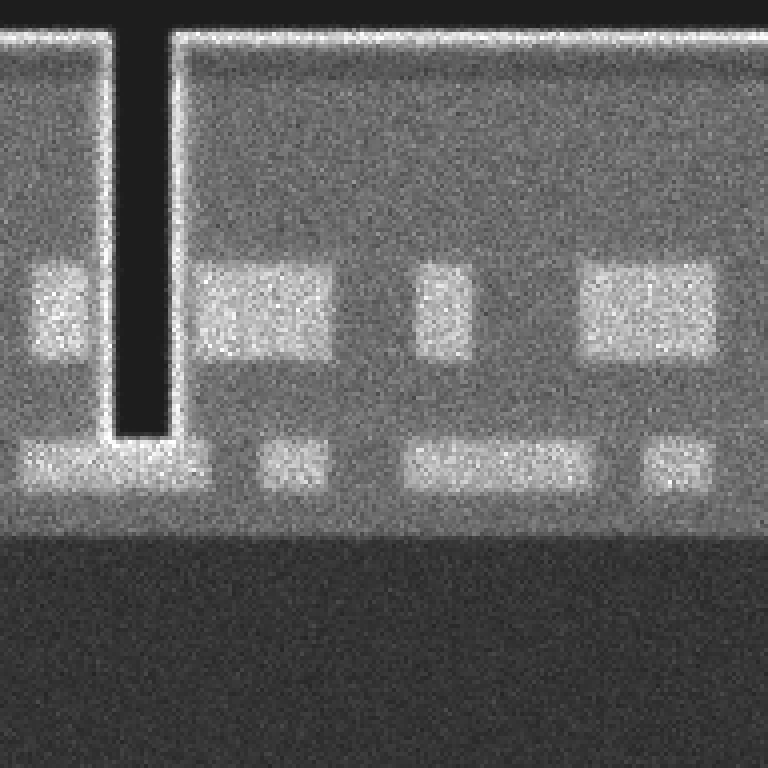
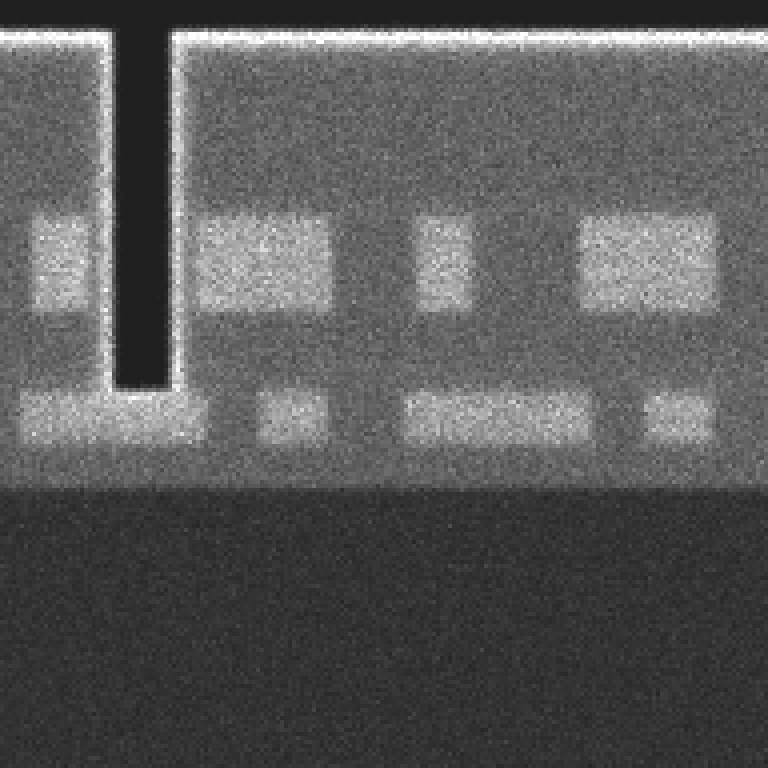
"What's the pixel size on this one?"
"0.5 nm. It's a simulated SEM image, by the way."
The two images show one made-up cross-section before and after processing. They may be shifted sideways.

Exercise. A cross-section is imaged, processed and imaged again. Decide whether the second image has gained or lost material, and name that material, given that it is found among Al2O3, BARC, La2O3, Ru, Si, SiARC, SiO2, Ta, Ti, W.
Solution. removed: SiARC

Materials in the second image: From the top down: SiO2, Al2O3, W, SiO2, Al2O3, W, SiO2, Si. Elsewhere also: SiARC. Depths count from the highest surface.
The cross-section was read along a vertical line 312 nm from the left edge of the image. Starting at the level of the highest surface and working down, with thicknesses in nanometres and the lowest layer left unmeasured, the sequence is SiO2 82, Al2O3 10, W 48, SiO2 24, Al2O3 16, SiO2 48, Si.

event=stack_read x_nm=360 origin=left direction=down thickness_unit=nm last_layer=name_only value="SiO2 82, Al2O3 10, SiO2 72, Al2O3 16, SiO2 48, Si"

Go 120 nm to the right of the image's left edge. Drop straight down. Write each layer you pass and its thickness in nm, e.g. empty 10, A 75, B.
SiO2 82, Al2O3 10, W 48, SiO2 24, Al2O3 16, SiO2 48, Si